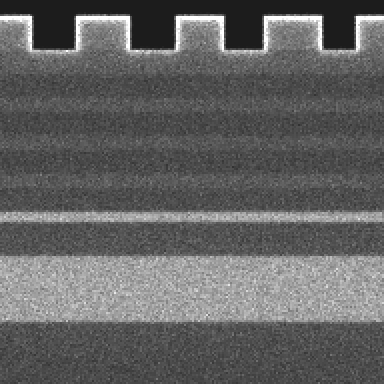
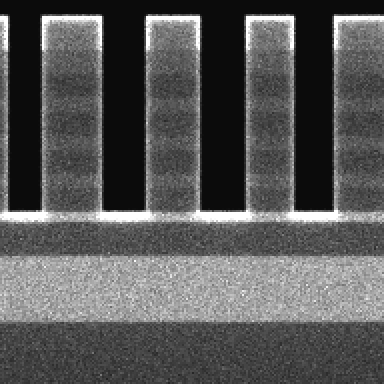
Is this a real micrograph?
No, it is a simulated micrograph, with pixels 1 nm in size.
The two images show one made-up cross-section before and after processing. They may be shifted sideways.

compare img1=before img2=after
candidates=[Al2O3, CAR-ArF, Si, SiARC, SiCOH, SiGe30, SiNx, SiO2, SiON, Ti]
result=removed:Si and SiGe30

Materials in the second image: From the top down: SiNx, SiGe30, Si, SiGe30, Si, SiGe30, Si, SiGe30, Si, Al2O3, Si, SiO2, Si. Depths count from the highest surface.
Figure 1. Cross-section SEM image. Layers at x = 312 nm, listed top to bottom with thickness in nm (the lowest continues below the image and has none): empty 196, Al2O3 10, Si 34, SiO2 66, Si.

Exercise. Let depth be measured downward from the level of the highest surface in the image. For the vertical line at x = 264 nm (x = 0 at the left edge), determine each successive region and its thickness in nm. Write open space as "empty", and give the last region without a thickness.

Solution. SiNx 34, SiGe30 24, Si 24, SiGe30 14, Si 24, SiGe30 14, Si 24, SiGe30 14, Si 24, Al2O3 10, Si 34, SiO2 66, Si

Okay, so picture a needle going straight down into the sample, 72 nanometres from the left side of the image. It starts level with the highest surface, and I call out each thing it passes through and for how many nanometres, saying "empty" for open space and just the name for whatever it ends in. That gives SiNx 34, SiGe30 24, Si 24, SiGe30 14, Si 24, SiGe30 14, Si 24, SiGe30 14, Si 24, Al2O3 10, Si 34, SiO2 66, Si